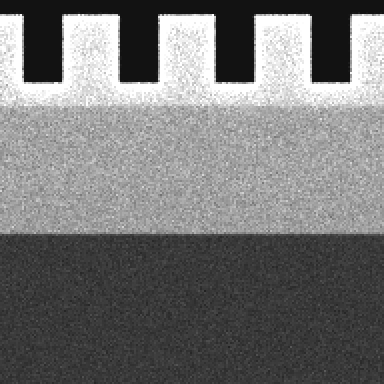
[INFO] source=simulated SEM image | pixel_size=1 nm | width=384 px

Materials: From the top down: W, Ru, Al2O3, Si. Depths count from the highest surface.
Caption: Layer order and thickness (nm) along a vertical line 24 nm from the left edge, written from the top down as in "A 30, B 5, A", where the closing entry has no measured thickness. empty 68, W 22, Ru 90, Al2O3 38, Si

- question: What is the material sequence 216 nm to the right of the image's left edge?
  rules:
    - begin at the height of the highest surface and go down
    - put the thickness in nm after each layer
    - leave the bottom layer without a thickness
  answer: empty 68, W 22, Ru 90, Al2O3 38, Si